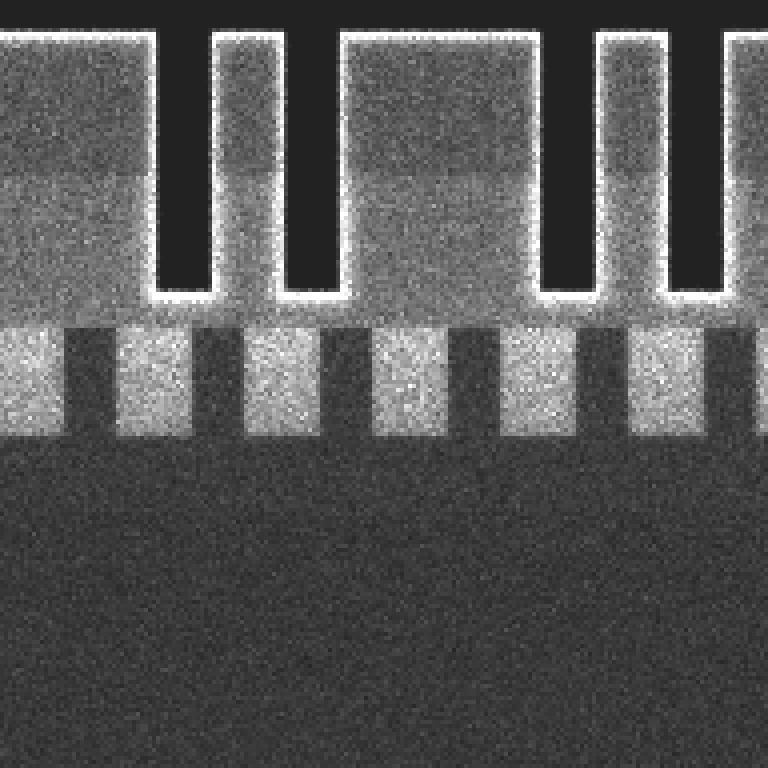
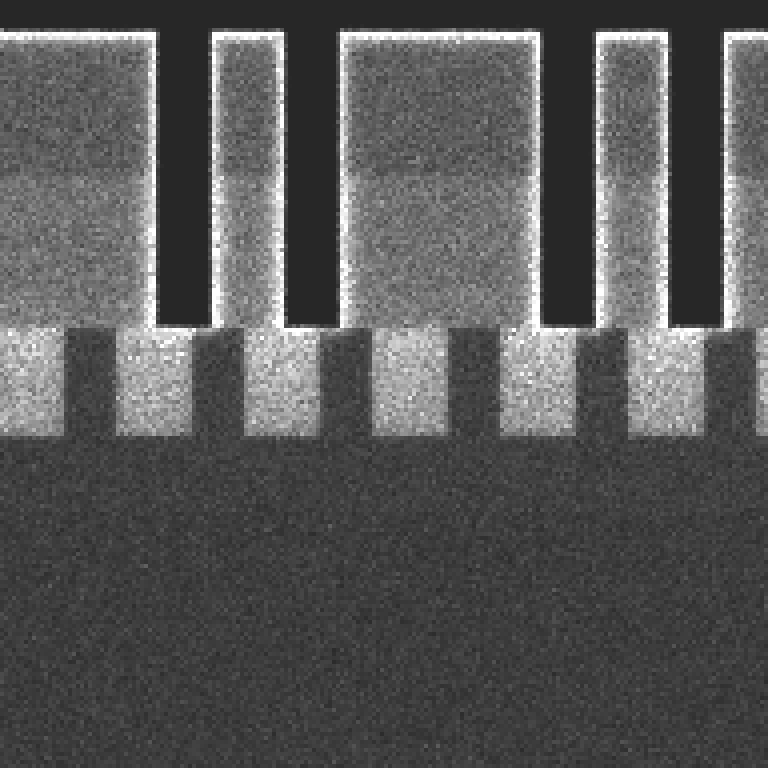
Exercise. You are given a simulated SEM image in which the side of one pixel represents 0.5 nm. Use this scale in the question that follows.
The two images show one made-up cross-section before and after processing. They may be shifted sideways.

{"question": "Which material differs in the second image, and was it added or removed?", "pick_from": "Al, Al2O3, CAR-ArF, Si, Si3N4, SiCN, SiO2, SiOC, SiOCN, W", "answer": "Al2O3, removed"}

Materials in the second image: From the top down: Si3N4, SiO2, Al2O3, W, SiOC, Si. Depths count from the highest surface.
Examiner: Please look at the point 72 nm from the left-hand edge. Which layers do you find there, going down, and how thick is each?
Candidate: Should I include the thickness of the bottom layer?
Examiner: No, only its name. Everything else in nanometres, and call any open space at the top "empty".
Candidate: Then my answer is Si3N4 72, SiO2 58, Al2O3 18, W 54, SiOC 38, Si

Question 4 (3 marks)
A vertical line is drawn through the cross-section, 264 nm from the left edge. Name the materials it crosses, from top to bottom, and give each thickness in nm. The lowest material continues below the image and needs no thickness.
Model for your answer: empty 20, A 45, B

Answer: Si3N4 72, SiO2 58, Al2O3 18, W 54, SiOC 38, Si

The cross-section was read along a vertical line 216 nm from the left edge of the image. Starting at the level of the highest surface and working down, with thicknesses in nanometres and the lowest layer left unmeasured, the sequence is Si3N4 72, SiO2 58, Al2O3 18, W 54, SiOC 38, Si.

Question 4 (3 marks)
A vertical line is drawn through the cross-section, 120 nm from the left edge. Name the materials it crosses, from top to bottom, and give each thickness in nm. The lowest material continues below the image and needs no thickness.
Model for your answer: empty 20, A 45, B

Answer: Si3N4 72, SiO2 58, Al2O3 18, SiOC 92, Si